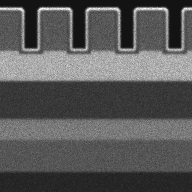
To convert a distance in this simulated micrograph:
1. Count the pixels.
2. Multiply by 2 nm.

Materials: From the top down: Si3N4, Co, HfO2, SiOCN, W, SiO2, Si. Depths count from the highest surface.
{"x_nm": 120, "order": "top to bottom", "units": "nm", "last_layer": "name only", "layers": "Si3N4 10, Co 76, HfO2 60, SiOCN 76, W 42, SiO2 64, Si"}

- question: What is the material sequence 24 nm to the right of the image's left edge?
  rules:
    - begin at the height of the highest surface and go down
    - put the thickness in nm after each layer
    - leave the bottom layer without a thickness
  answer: Si3N4 10, Co 76, HfO2 60, SiOCN 76, W 42, SiO2 64, Si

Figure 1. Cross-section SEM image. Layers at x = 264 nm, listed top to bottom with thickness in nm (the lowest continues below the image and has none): empty 82, Si3N4 10, HfO2 54, SiOCN 76, W 42, SiO2 64, Si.